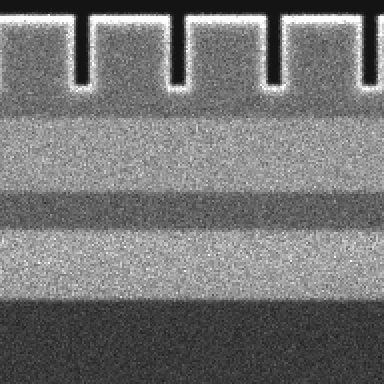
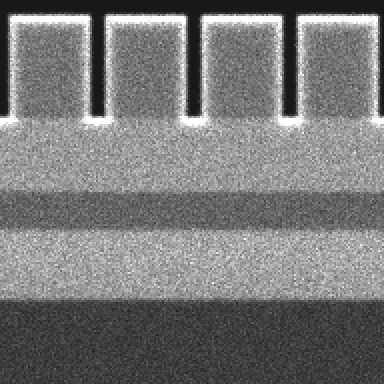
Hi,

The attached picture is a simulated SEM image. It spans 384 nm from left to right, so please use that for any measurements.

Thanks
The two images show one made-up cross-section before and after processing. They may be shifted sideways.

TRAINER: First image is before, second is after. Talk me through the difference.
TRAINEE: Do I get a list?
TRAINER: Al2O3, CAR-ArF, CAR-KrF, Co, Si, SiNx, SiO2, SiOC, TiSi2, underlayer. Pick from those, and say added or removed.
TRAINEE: removed: underlayer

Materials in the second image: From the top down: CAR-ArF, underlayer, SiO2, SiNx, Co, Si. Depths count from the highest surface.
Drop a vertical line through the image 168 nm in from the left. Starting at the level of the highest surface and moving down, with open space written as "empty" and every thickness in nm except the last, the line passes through CAR-ArF 70, underlayer 32, SiO2 74, SiNx 38, Co 70, Si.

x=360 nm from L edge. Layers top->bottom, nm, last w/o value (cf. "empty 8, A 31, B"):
CAR-ArF 70, underlayer 32, SiO2 74, SiNx 38, Co 70, Si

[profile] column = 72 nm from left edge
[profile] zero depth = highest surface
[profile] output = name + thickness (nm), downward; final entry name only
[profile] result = CAR-ArF 70, underlayer 32, SiO2 74, SiNx 38, Co 70, Si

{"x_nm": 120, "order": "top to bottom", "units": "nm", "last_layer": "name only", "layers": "CAR-ArF 70, underlayer 32, SiO2 74, SiNx 38, Co 70, Si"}